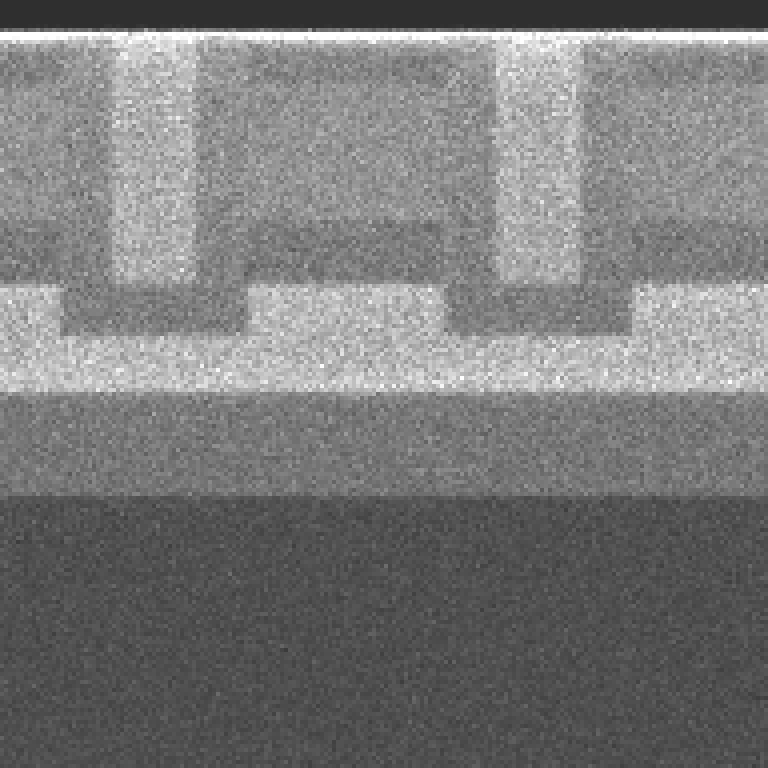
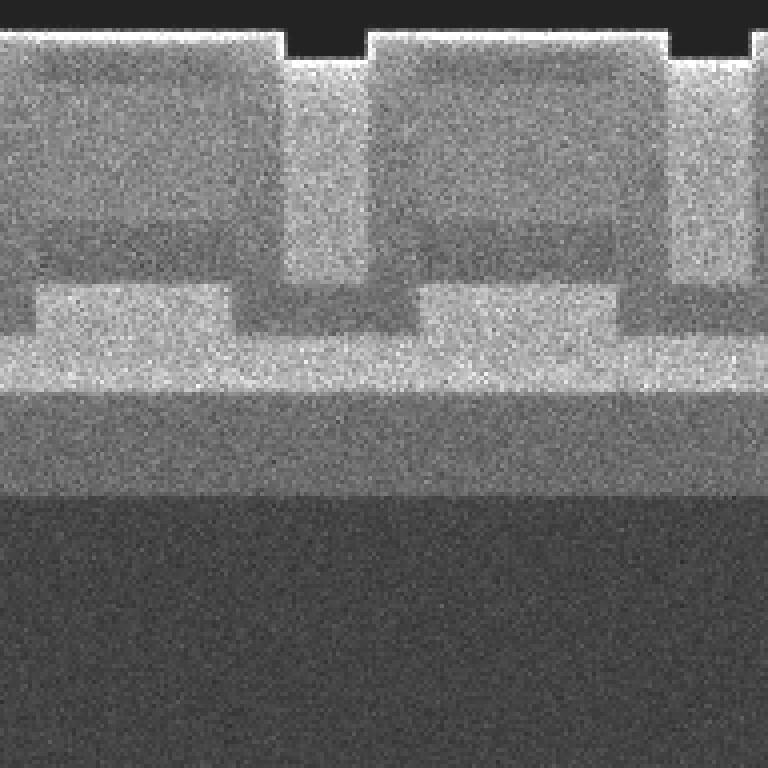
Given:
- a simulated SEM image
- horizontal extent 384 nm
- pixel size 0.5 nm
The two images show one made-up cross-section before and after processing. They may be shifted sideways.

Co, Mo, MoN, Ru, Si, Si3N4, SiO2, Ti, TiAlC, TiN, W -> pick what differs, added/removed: Ru removed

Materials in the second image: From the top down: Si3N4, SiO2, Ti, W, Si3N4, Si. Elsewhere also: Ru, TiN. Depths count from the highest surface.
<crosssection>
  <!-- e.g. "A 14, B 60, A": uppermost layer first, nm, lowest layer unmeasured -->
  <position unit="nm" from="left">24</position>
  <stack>Si3N4 26, SiO2 68, Ti 32, W 54, Si3N4 52, Si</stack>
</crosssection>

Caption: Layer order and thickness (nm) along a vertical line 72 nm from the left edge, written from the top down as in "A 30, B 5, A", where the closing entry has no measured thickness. Si3N4 26, SiO2 68, Ti 32, W 54, Si3N4 52, Si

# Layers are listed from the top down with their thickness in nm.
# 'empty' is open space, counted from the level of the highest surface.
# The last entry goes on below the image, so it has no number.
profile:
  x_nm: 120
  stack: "TiN 152, W 28, Si3N4 52, Si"